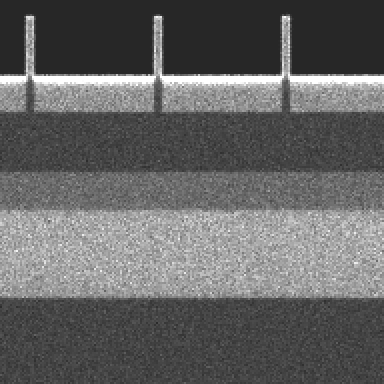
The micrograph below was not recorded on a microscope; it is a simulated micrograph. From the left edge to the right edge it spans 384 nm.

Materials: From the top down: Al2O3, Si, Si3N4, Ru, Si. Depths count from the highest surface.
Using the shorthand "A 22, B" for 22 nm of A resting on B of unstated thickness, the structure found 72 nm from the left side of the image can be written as empty 60, Al2O3 36, Si 60, Si3N4 38, Ru 88, Si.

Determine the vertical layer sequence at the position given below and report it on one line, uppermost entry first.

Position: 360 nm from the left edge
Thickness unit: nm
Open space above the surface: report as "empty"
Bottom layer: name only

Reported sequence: empty 60, Al2O3 36, Si 60, Si3N4 38, Ru 88, Si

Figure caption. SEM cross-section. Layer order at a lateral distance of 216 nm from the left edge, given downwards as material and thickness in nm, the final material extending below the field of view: empty 60, Al2O3 36, Si 60, Si3N4 38, Ru 88, Si